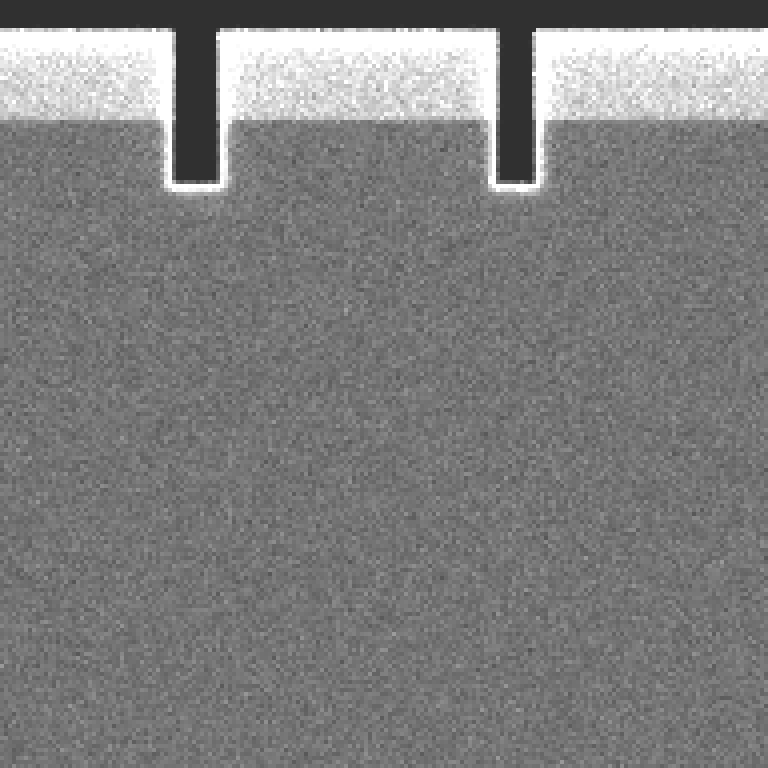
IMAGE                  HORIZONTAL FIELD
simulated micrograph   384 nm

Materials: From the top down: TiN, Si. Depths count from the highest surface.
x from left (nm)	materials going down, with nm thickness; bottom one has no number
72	TiN 44, Si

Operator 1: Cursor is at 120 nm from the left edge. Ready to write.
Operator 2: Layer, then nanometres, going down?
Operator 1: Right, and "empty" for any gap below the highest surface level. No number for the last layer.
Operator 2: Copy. TiN 44, Si